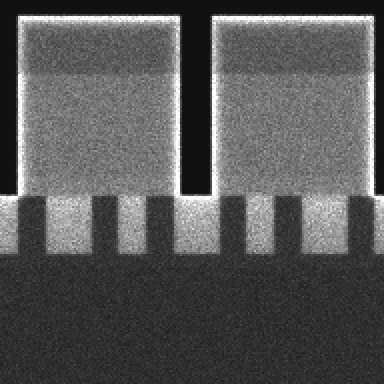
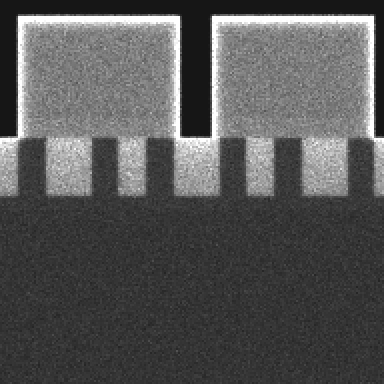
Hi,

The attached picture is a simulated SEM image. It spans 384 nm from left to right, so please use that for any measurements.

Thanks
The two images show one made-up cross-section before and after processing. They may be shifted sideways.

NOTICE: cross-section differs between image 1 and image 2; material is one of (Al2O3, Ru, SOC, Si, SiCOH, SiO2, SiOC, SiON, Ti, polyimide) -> removed: SOC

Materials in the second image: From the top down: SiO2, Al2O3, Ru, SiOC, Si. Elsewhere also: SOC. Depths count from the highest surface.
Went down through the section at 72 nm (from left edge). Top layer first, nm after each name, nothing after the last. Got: SiO2 102, Al2O3 20, Ru 58, SiOC 14, Si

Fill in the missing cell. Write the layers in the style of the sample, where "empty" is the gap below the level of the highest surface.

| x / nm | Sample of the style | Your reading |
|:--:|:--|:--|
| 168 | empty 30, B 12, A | SiO2 102, Al2O3 20, SiOC 72, Si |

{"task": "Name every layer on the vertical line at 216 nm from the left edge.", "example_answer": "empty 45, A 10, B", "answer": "SiO2 102, Al2O3 20, Ru 58, SiOC 14, Si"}